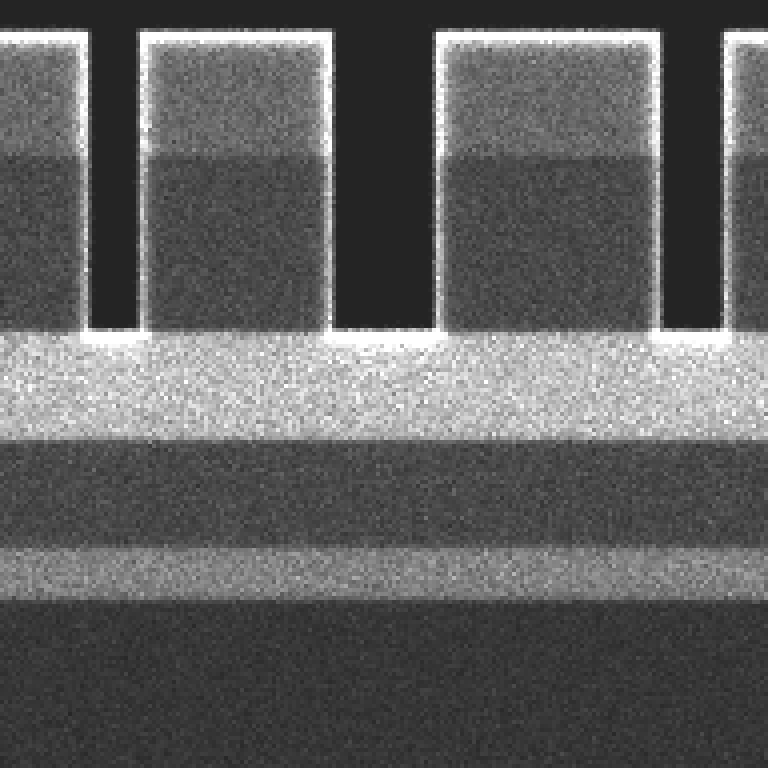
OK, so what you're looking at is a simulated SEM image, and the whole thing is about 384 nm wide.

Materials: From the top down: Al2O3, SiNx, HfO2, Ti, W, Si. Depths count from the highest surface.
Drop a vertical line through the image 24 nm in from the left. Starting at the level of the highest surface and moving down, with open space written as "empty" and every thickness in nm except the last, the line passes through Al2O3 62, SiNx 88, HfO2 54, Ti 54, W 26, Si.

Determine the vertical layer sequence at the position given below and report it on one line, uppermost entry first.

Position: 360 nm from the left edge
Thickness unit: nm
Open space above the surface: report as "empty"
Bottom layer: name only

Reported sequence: empty 150, HfO2 54, Ti 54, W 26, Si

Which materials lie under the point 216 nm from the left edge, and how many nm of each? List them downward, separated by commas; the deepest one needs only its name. empty 150, HfO2 54, Ti 54, W 26, Si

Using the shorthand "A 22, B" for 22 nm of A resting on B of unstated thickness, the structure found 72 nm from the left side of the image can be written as Al2O3 62, SiNx 88, HfO2 54, Ti 54, W 26, Si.